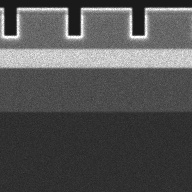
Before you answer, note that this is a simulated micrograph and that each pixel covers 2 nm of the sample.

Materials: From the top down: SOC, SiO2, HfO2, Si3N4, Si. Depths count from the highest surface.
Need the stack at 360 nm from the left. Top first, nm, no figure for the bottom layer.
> SOC 14, SiO2 68, HfO2 38, Si3N4 88, Si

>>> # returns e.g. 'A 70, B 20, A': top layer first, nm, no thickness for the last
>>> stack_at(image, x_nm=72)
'SOC 14, SiO2 68, HfO2 38, Si3N4 88, Si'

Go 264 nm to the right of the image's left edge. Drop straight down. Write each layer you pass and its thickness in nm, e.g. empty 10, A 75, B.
empty 56, SiO2 26, HfO2 38, Si3N4 88, Si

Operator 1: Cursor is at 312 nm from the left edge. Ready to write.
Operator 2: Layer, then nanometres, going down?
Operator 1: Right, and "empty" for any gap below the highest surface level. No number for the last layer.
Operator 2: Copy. SOC 14, SiO2 68, HfO2 38, Si3N4 88, Si